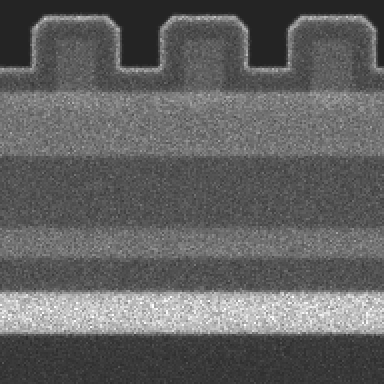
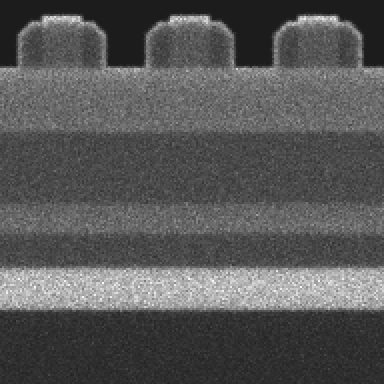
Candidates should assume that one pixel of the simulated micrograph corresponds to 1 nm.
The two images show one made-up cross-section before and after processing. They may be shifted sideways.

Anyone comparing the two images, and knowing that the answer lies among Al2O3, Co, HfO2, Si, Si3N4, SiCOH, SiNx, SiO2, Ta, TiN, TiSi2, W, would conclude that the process removed SiNx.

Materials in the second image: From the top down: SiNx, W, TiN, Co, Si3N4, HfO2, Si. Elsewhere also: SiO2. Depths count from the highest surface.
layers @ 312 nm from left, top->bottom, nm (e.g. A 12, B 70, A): SiO2 52, W 64, TiN 72, Co 30, Si3N4 34, HfO2 42, Si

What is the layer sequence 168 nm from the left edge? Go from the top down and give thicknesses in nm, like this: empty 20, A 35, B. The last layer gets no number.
empty 6, SiNx 46, W 64, TiN 72, Co 30, Si3N4 34, HfO2 42, Si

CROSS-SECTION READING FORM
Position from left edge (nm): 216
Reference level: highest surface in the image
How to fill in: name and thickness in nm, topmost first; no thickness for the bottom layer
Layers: empty 6, SiNx 46, W 64, TiN 72, Co 30, Si3N4 34, HfO2 42, Si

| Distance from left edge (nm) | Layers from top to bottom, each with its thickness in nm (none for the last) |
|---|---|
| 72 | SiO2 52, W 64, TiN 72, Co 30, Si3N4 34, HfO2 42, Si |